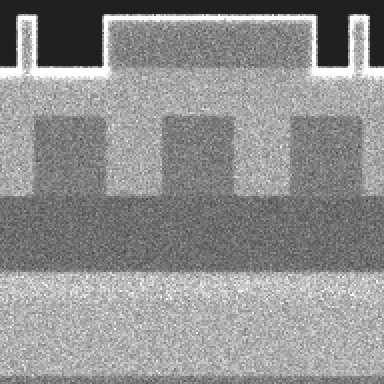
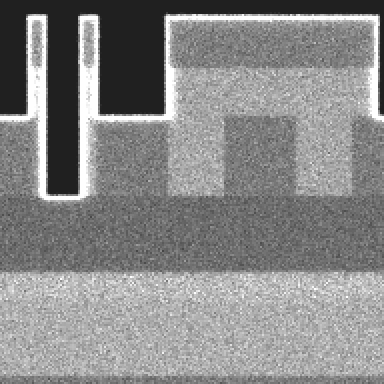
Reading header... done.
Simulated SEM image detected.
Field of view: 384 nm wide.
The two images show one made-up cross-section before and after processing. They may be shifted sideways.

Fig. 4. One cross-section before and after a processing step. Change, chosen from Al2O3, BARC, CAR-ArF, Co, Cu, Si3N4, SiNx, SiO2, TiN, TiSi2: SiO2 removed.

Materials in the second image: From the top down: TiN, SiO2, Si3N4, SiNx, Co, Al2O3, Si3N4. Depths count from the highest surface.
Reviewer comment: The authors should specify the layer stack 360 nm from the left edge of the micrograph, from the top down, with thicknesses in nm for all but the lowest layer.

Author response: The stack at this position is TiN 52, SiO2 48, Si3N4 80, SiNx 76, Co 28, Al2O3 76, Si3N4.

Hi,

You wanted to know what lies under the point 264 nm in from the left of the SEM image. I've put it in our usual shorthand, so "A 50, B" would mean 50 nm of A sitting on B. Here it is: TiN 52, SiO2 48, Si3N4 80, SiNx 76, Co 28, Al2O3 76, Si3N4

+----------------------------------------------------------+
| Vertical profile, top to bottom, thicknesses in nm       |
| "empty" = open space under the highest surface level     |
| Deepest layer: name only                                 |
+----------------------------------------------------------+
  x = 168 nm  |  TiN 52, SiO2 128, SiNx 76, Co 28, Al2O3 76, Si3N4